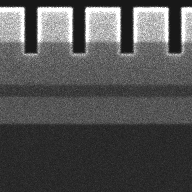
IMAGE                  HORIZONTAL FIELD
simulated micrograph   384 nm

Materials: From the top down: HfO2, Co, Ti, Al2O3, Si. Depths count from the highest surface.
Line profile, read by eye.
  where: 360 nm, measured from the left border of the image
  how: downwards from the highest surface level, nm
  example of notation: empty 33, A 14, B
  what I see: empty 92, Co 62, Ti 24, Al2O3 54, Si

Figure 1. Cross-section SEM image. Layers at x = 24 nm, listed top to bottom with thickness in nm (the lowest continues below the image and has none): HfO2 68, Co 86, Ti 24, Al2O3 54, Si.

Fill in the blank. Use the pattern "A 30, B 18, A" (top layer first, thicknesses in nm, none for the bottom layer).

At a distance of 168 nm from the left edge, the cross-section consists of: empty 92, Co 62, Ti 24, Al2O3 54, Si